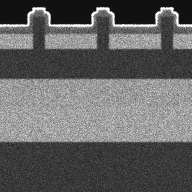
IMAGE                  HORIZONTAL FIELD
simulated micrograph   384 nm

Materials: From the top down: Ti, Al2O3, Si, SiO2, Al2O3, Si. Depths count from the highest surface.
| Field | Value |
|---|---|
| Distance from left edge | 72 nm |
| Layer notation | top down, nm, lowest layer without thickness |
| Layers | Ti 18, Si 124, SiO2 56, Al2O3 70, Si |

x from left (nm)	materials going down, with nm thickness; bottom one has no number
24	empty 34, Ti 18, Al2O3 30, Si 60, SiO2 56, Al2O3 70, Si